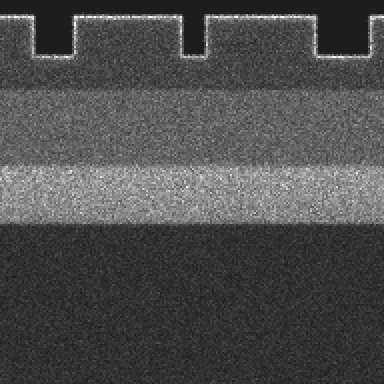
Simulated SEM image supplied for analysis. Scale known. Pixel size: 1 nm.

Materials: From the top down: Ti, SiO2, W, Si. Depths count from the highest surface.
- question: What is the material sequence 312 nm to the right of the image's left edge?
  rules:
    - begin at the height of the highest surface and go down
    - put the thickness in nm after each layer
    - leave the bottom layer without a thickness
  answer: Ti 74, SiO2 76, W 58, Si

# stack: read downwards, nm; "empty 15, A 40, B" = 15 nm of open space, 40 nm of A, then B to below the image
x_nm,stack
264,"Ti 74, SiO2 76, W 58, Si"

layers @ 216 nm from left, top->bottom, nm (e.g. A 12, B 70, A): Ti 74, SiO2 76, W 58, Si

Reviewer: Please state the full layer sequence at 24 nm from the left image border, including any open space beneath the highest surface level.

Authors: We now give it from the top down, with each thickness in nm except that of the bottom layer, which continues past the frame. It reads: Ti 74, SiO2 76, W 58, Si